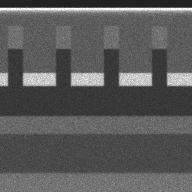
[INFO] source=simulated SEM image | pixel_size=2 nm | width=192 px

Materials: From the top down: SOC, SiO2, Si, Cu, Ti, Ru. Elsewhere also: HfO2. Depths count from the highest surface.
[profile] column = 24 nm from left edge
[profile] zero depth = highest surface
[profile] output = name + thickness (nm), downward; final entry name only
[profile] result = SOC 36, SiO2 46, Si 134, Cu 36, Ti 78, Ru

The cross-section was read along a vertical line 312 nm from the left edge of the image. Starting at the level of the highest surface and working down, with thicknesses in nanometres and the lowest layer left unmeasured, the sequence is SOC 36, SiO2 46, Si 134, Cu 36, Ti 78, Ru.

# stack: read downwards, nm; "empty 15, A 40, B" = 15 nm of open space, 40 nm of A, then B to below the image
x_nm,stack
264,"SOC 130, HfO2 26, Si 60, Cu 36, Ti 78, Ru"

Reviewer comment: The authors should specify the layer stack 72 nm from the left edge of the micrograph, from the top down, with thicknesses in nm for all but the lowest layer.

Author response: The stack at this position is SOC 130, HfO2 26, Si 60, Cu 36, Ti 78, Ru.